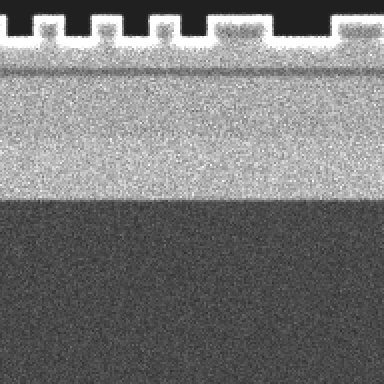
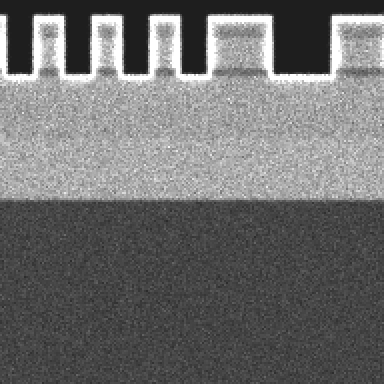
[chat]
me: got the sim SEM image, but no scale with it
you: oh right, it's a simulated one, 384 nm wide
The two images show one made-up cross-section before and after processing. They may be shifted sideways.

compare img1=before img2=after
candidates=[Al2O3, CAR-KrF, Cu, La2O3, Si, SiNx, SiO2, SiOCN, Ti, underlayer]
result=removed:SiNx and SiO2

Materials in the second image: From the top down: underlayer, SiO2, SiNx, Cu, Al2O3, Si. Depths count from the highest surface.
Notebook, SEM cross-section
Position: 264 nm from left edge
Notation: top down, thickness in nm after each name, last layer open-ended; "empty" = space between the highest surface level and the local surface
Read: underlayer 22, SiO2 30, SiNx 8, Cu 62, Al2O3 62, Si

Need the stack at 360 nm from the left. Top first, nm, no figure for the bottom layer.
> underlayer 22, SiO2 30, SiNx 8, Cu 62, Al2O3 62, Si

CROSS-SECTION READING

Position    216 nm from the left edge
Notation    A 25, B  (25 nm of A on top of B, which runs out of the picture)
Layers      underlayer 22, SiO2 30, SiNx 8, Cu 62, Al2O3 62, Si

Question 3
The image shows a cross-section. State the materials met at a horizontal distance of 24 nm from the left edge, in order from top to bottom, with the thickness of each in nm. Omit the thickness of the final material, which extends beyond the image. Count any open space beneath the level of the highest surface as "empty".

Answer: empty 60, Cu 62, Al2O3 62, Si